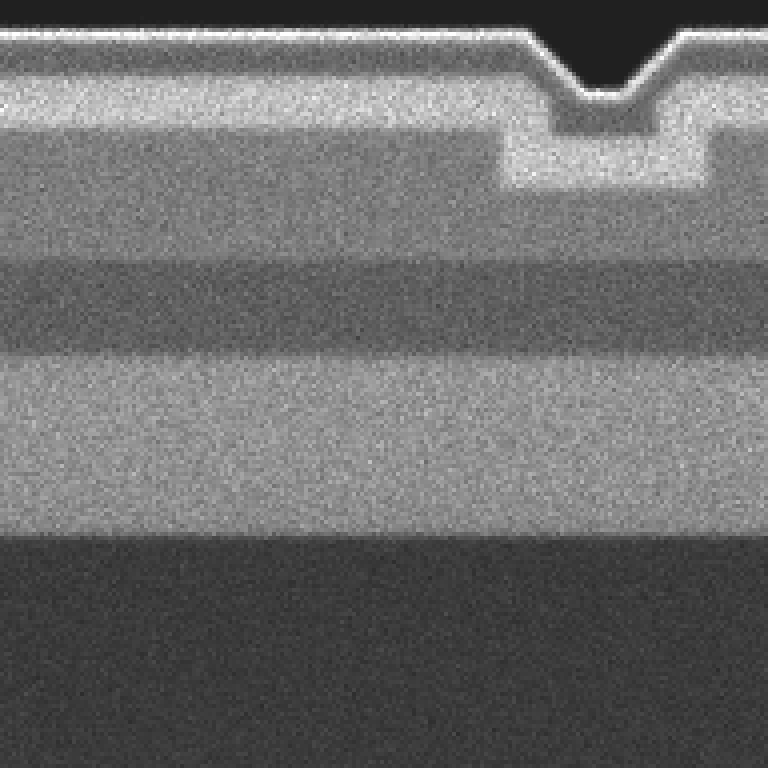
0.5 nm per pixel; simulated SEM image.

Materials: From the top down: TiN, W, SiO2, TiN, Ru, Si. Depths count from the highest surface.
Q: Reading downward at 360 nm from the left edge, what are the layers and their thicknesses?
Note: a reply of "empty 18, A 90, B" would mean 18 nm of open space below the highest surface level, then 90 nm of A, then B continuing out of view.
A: TiN 22, W 26, SiO2 66, TiN 48, Ru 90, Si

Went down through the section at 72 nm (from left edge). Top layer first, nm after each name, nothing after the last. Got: TiN 22, W 26, SiO2 66, TiN 48, Ru 90, Si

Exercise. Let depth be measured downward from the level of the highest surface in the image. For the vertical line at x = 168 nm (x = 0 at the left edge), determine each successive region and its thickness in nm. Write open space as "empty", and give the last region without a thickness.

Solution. TiN 22, W 26, SiO2 66, TiN 48, Ru 90, Si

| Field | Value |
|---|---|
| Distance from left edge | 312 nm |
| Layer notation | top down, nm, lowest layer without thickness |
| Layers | empty 30, TiN 22, W 26, SiO2 36, TiN 48, Ru 90, Si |